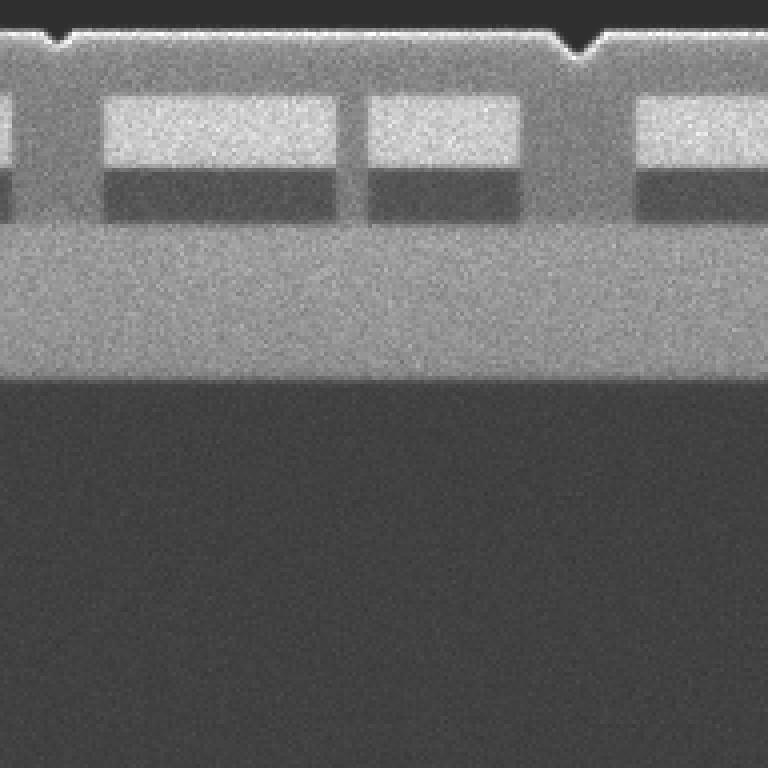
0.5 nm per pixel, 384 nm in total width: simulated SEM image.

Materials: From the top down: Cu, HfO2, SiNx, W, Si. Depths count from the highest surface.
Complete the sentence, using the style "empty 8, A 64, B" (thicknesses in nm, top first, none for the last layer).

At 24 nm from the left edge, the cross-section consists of empty 4, Cu 92, W 78, Si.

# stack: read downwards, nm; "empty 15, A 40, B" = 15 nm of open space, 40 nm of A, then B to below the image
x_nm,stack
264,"Cu 96, W 78, Si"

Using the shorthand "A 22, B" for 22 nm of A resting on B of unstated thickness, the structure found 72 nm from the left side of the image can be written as Cu 32, HfO2 36, SiNx 28, W 78, Si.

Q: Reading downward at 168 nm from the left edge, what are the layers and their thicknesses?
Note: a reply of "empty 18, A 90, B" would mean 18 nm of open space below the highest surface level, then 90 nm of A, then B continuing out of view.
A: Cu 96, W 78, Si